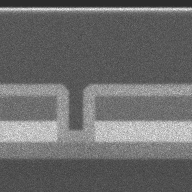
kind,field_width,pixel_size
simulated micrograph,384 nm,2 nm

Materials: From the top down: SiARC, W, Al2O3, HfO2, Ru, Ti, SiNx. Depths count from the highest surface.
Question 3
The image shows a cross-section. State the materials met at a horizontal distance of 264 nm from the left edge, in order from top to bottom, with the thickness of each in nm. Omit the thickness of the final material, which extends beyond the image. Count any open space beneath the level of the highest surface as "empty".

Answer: SiARC 152, W 24, Al2O3 50, HfO2 42, Ru 34, Ti 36, SiNx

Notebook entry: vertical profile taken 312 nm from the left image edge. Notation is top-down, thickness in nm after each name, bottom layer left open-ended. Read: SiARC 152, W 24, Al2O3 50, HfO2 42, Ru 34, Ti 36, SiNx